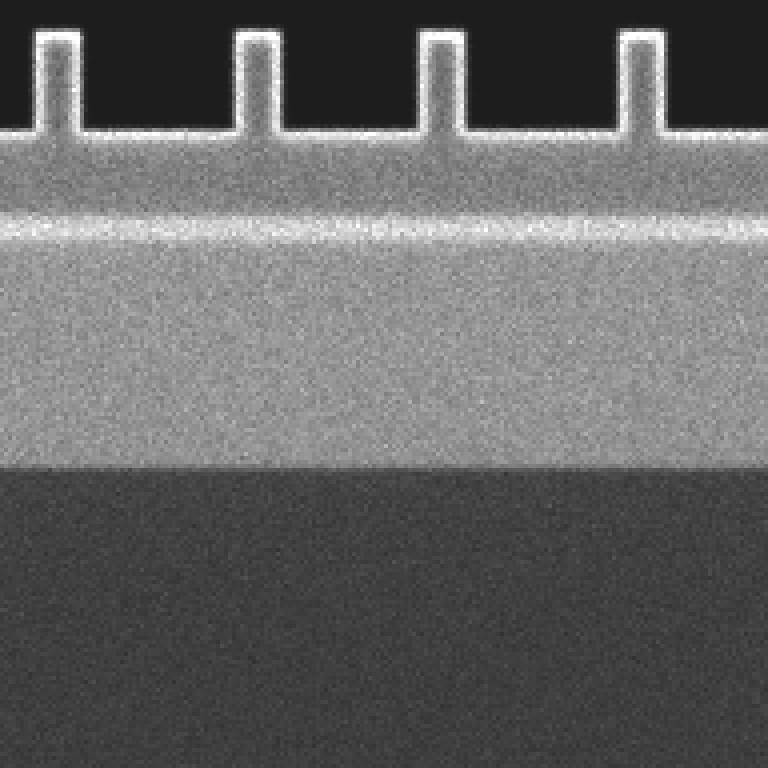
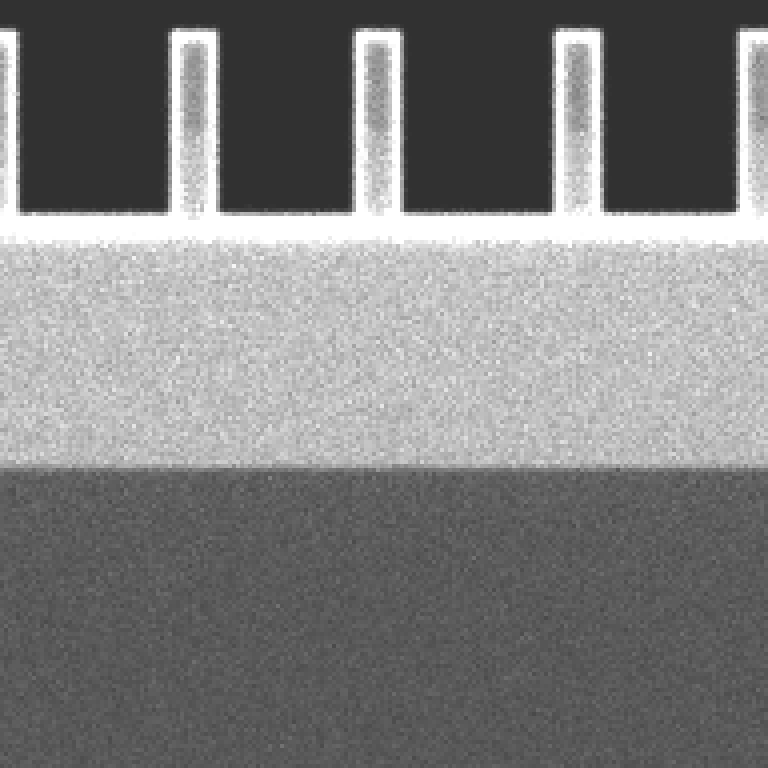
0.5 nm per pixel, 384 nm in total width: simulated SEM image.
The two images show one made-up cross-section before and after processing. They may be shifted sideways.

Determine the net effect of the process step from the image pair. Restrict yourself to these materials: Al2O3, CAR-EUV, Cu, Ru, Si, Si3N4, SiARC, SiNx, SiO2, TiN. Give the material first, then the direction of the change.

TiN: removed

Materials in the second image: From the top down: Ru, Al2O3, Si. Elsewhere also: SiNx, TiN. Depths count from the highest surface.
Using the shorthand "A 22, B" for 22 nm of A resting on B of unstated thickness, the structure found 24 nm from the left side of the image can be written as empty 92, Ru 12, Al2O3 114, Si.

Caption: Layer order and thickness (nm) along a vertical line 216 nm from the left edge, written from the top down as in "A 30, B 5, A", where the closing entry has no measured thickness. empty 92, Ru 12, Al2O3 114, Si